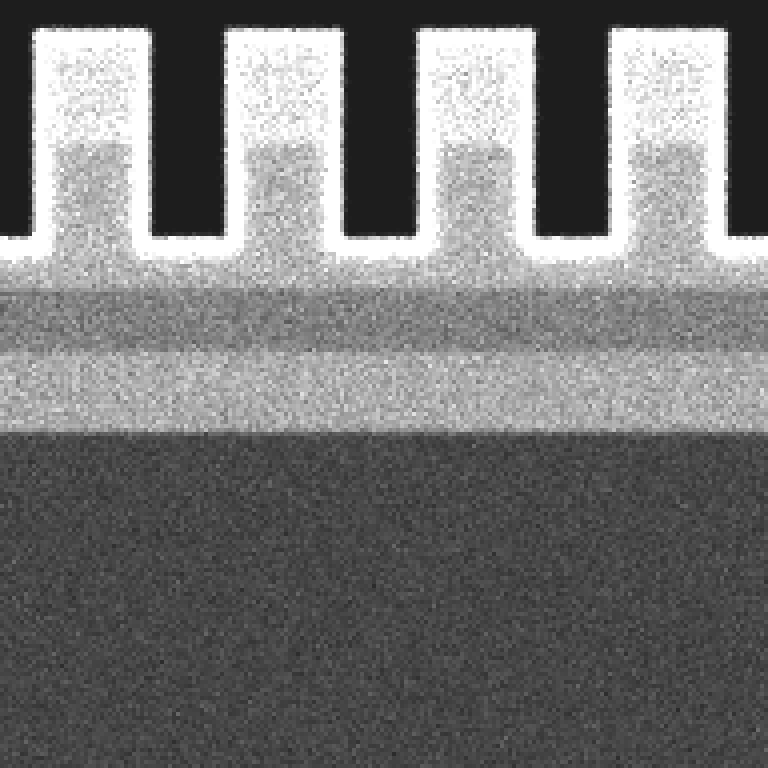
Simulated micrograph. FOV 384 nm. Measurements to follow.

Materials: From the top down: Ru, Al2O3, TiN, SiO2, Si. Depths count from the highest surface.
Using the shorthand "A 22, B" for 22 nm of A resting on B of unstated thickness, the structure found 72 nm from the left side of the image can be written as Ru 56, Al2O3 72, TiN 32, SiO2 40, Si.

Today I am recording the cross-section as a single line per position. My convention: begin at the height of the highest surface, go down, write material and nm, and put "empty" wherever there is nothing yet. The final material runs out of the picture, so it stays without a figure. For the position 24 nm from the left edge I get Ru 56, Al2O3 72, TiN 32, SiO2 40, Si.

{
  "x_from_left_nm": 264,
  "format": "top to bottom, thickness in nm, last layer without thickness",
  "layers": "Ru 56, Al2O3 72, TiN 32, SiO2 40, Si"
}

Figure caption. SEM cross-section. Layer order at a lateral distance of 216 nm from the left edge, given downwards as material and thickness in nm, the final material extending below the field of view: Ru 56, Al2O3 72, TiN 32, SiO2 40, Si